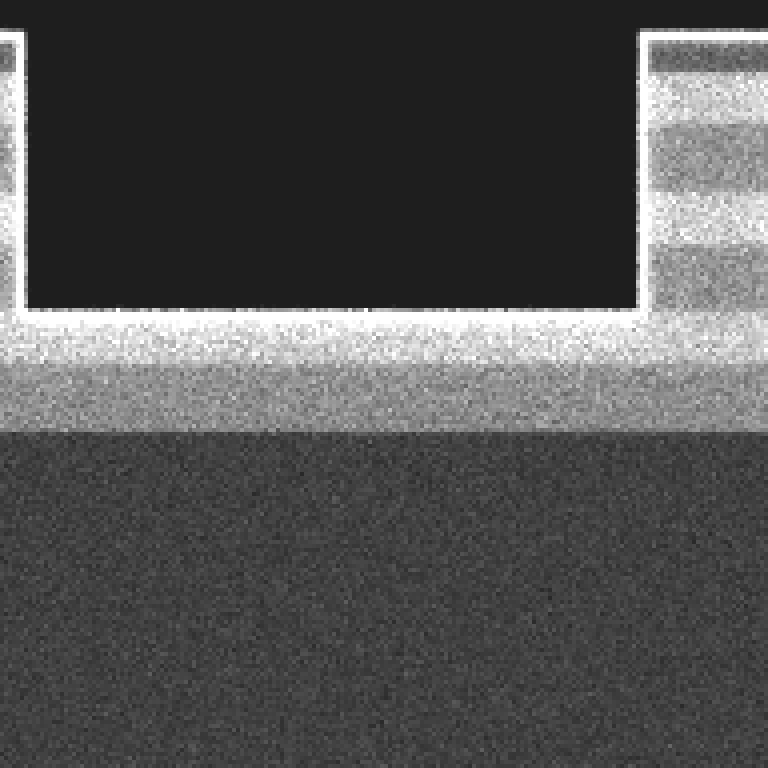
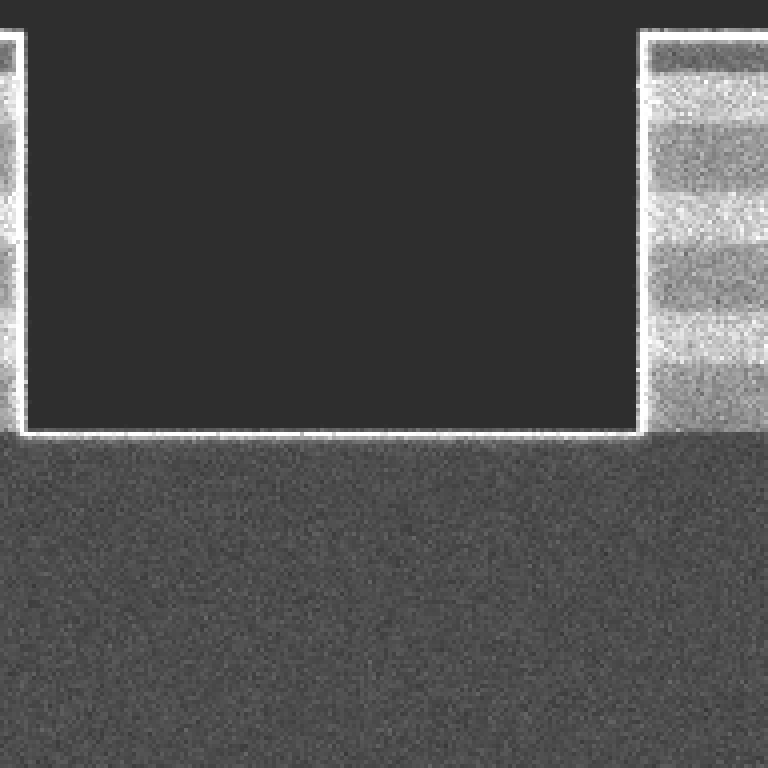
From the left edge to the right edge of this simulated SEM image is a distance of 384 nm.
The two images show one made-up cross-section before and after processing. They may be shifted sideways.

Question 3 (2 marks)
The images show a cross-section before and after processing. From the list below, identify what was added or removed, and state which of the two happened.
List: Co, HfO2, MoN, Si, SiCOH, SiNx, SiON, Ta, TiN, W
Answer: Co and W was removed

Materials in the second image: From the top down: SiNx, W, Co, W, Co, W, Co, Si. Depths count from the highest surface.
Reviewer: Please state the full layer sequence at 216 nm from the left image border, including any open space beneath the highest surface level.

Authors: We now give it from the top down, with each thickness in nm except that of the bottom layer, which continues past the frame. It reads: empty 200, Si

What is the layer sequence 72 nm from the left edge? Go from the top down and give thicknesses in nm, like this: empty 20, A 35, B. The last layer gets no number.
empty 200, Si